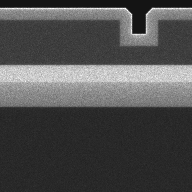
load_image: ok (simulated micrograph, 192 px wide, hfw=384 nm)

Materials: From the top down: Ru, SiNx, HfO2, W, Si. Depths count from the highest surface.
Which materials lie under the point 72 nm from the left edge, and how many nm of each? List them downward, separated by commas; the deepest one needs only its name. Ru 24, SiNx 90, HfO2 34, W 50, Si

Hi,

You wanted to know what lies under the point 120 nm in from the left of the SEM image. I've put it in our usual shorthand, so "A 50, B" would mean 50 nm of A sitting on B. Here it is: Ru 24, SiNx 90, HfO2 34, W 50, Si